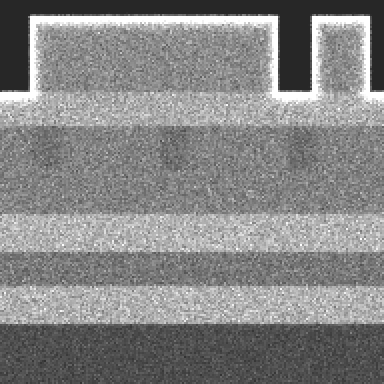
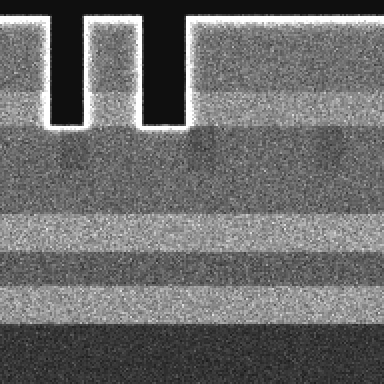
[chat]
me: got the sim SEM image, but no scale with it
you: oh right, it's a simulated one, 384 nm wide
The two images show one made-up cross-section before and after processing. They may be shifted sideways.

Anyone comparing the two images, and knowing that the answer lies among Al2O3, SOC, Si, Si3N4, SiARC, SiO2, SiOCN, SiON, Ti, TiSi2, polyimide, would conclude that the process removed SiO2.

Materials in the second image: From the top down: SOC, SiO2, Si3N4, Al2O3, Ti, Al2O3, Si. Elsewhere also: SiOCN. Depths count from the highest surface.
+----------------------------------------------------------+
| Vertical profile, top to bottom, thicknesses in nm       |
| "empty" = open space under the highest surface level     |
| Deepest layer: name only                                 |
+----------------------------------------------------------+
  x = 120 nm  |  SOC 76, SiO2 34, Si3N4 88, Al2O3 38, Ti 34, Al2O3 38, Si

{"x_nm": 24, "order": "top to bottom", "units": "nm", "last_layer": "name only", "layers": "SOC 76, SiO2 34, Si3N4 88, Al2O3 38, Ti 34, Al2O3 38, Si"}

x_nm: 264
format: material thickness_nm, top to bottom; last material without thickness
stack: SOC 76, SiO2 34, Si3N4 88, Al2O3 38, Ti 34, Al2O3 38, Si